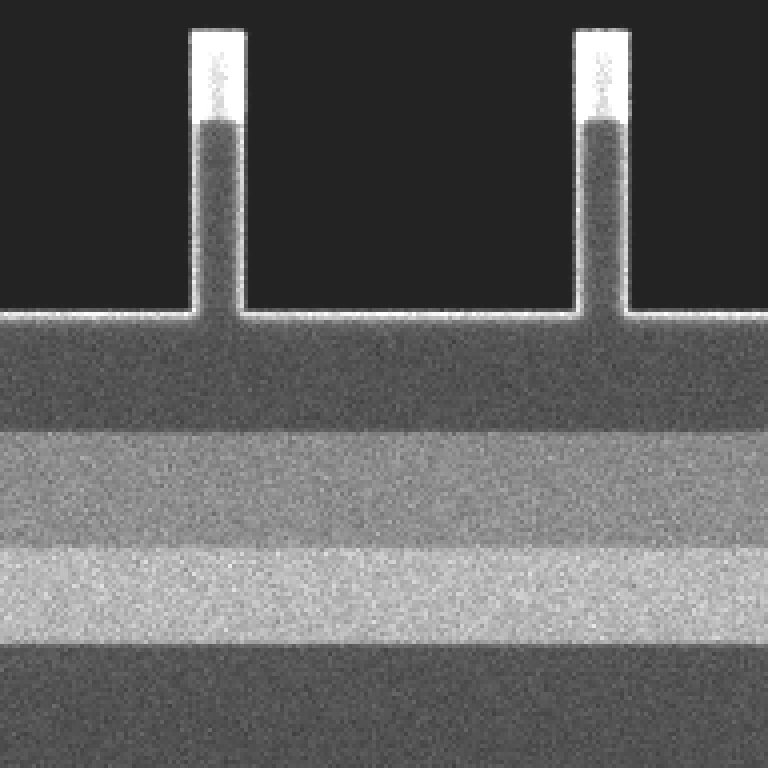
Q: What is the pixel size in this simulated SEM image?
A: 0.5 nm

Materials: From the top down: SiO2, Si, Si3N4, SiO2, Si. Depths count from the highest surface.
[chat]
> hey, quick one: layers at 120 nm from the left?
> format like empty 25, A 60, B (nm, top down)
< SiO2 44, Si 156, Si3N4 58, SiO2 48, Si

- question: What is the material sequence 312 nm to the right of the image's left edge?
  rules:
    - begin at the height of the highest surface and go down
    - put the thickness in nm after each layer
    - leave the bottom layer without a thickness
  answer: SiO2 44, Si 156, Si3N4 58, SiO2 48, Si